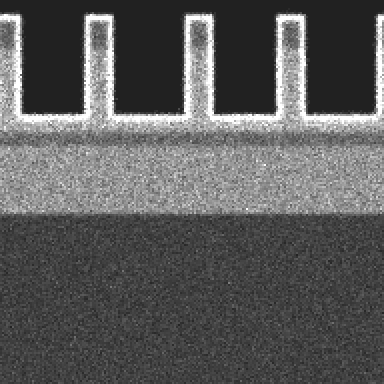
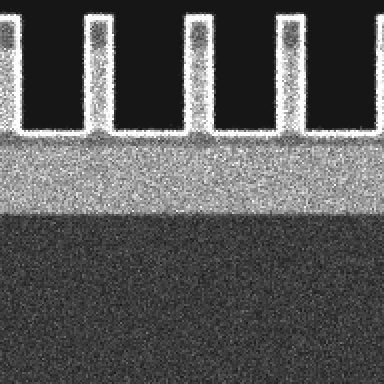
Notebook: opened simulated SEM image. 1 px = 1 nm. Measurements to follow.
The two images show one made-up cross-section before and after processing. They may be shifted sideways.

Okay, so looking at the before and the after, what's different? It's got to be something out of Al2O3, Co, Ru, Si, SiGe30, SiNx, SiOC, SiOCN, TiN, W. Ru, removed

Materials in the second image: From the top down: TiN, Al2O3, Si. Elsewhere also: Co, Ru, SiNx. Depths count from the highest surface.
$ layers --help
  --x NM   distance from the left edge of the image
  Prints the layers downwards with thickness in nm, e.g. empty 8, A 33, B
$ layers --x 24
empty 116, TiN 14, Al2O3 68, Si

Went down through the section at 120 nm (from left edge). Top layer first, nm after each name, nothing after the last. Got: empty 116, TiN 14, Al2O3 68, Si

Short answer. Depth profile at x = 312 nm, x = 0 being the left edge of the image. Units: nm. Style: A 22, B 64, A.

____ empty 116, TiN 14, Al2O3 68, Si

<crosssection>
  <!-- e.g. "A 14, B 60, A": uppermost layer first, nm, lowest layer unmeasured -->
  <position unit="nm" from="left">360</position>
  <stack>empty 116, TiN 14, Al2O3 68, Si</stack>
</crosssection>